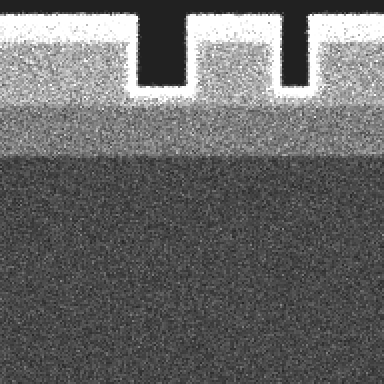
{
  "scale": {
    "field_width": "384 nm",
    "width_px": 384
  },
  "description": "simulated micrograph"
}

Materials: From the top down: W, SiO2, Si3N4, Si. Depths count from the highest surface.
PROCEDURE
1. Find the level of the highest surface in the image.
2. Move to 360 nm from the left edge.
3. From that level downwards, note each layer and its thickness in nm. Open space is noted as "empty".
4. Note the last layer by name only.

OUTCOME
W 26, SiO2 64, Si3N4 50, Si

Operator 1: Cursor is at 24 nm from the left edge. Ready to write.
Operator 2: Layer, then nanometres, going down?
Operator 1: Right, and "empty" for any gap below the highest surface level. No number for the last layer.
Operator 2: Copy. W 26, SiO2 64, Si3N4 50, Si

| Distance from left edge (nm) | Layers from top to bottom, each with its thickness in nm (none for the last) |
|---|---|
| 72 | W 26, SiO2 64, Si3N4 50, Si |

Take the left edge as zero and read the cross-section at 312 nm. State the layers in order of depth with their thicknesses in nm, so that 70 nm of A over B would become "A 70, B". W 26, SiO2 64, Si3N4 50, Si